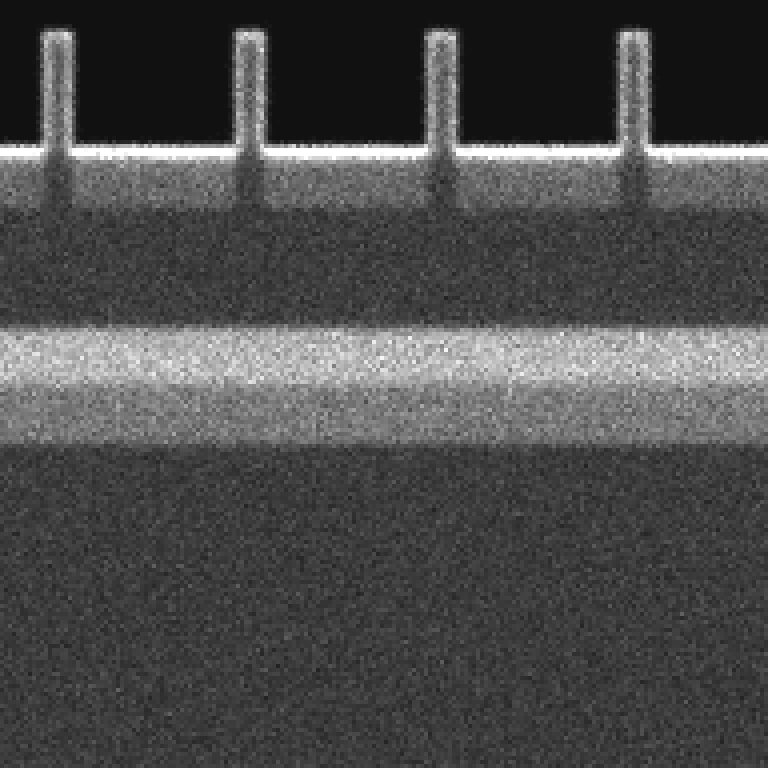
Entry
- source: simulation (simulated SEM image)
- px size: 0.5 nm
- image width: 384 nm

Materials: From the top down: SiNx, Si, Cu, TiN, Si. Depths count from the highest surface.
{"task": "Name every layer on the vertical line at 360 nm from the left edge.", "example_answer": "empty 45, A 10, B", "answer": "empty 58, SiNx 30, Si 60, Cu 28, TiN 30, Si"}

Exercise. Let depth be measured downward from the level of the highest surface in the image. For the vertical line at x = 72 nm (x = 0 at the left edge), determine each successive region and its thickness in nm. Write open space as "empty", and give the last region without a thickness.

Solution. empty 58, SiNx 30, Si 60, Cu 28, TiN 30, Si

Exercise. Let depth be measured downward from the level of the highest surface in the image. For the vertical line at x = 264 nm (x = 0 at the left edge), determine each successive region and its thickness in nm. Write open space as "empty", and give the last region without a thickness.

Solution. empty 58, SiNx 30, Si 60, Cu 28, TiN 30, Si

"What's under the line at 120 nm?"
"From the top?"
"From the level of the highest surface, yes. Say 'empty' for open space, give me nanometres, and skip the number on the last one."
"Si 148, Cu 28, TiN 30, Si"